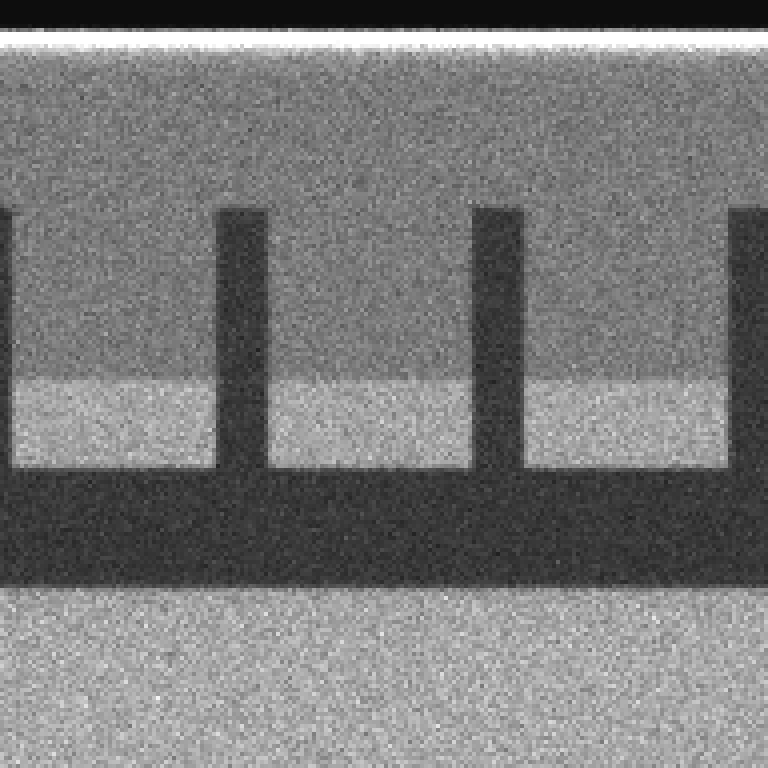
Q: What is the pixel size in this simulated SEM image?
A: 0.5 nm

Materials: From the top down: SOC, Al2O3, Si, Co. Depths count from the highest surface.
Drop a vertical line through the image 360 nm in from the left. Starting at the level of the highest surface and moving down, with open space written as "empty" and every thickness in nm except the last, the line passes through SOC 174, Al2O3 44, Si 60, Co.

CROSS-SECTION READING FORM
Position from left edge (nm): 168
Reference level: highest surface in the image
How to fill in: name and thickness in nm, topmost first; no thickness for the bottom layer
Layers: SOC 174, Al2O3 44, Si 60, Co